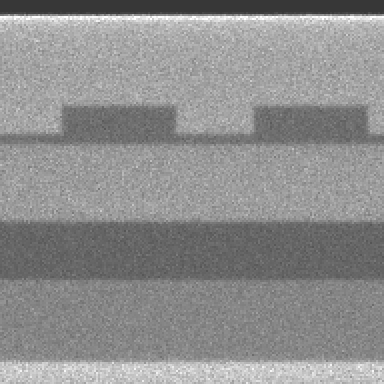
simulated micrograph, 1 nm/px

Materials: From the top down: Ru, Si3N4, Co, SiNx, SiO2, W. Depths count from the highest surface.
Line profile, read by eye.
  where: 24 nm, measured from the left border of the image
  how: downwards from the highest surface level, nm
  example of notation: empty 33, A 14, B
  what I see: Ru 118, Si3N4 10, Co 78, SiNx 58, SiO2 82, W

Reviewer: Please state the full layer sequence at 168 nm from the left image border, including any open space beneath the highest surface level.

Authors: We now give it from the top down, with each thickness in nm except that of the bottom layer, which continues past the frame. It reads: Ru 90, Si3N4 38, Co 78, SiNx 58, SiO2 82, W